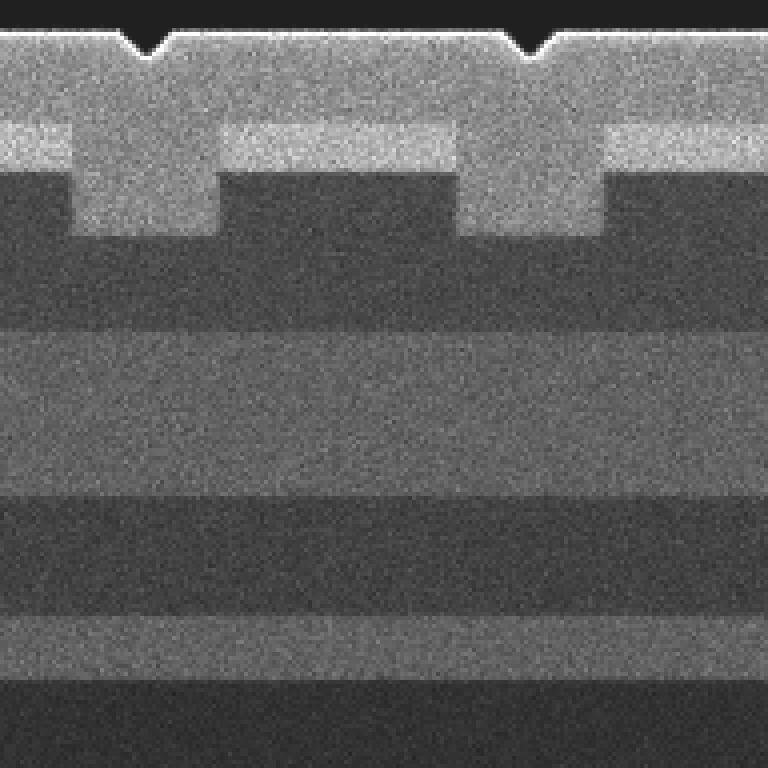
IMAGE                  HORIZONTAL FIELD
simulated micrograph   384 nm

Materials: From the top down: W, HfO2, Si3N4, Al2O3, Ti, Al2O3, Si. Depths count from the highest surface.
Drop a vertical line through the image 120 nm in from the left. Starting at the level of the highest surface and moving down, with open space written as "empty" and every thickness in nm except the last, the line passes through W 46, HfO2 24, Si3N4 80, Al2O3 82, Ti 60, Al2O3 32, Si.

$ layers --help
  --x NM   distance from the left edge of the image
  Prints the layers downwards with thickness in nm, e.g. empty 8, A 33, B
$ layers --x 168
W 46, HfO2 24, Si3N4 80, Al2O3 82, Ti 60, Al2O3 32, Si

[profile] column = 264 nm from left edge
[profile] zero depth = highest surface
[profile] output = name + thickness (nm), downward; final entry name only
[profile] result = empty 12, W 90, Si3N4 48, Al2O3 82, Ti 60, Al2O3 32, Si